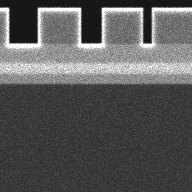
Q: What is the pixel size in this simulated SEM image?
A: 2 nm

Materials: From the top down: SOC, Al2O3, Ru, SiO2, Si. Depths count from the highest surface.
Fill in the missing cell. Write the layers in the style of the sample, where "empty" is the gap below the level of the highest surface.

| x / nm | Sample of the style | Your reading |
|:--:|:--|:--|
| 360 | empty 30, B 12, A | SOC 72, Al2O3 38, Ru 22, SiO2 20, Si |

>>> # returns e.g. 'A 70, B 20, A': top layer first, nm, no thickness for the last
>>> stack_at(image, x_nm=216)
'SOC 72, Al2O3 38, Ru 22, SiO2 20, Si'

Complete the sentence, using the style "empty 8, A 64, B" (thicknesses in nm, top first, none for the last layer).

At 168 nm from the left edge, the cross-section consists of empty 72, Al2O3 38, Ru 22, SiO2 20, Si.